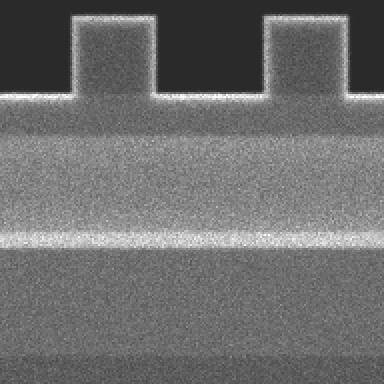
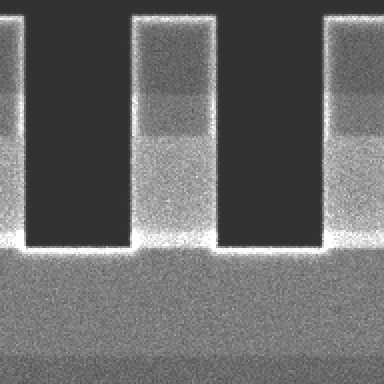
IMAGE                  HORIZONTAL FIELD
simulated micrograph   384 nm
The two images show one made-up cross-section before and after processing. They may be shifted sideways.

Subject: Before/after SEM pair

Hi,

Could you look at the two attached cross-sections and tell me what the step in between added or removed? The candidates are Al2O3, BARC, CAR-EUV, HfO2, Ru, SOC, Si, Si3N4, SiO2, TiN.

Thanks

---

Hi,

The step removed HfO2 and Ru and SiO2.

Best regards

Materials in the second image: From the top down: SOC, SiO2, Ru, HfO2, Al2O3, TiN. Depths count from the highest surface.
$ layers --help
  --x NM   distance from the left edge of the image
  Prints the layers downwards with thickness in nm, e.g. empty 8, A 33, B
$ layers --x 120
empty 232, Al2O3 108, TiN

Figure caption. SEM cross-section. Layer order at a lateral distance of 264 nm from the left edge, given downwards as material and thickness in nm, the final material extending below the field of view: empty 232, Al2O3 108, TiN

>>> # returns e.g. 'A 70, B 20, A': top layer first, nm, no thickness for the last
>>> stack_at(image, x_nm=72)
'empty 232, Al2O3 108, TiN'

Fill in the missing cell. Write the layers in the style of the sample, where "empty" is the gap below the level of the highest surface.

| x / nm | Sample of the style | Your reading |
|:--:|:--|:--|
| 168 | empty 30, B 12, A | SOC 78, SiO2 42, Ru 96, HfO2 16, Al2O3 108, TiN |